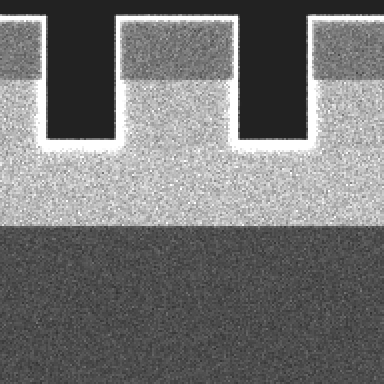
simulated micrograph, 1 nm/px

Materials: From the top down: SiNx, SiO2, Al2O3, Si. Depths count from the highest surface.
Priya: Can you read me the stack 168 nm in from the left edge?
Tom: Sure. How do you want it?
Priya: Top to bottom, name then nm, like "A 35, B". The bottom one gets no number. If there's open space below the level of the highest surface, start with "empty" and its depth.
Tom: SiNx 64, SiO2 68, Al2O3 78, Si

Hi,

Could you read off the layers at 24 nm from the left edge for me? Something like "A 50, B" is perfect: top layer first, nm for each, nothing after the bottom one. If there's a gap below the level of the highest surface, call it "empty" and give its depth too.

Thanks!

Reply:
SiNx 64, SiO2 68, Al2O3 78, Si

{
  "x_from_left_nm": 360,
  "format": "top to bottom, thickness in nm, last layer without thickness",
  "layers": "SiNx 64, SiO2 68, Al2O3 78, Si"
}